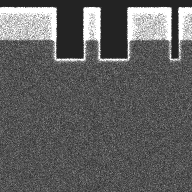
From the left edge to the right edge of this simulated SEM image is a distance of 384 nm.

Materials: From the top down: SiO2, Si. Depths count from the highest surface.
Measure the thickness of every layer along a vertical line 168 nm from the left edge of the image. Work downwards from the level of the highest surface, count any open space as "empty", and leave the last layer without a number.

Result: SiO2 64, Si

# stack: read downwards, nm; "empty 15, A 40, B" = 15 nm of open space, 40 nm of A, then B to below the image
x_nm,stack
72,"SiO2 64, Si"